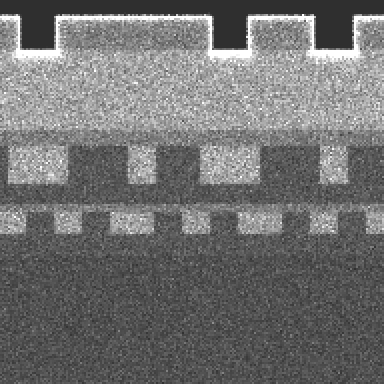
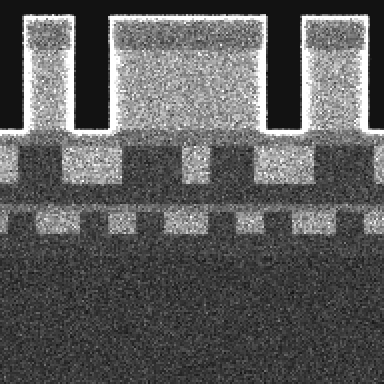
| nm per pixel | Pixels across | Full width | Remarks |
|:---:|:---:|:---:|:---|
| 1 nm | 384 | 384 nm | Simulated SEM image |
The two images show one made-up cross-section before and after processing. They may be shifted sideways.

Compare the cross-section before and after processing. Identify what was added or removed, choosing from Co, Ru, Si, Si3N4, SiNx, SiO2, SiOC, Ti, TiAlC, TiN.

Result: SiO2 removed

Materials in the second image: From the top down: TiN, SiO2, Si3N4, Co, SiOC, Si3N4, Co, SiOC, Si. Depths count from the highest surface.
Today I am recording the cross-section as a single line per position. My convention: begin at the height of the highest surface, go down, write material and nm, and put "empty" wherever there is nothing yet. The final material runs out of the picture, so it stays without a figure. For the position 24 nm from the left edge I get TiN 34, SiO2 80, Si3N4 16, SiOC 58, Si3N4 8, SiOC 44, Si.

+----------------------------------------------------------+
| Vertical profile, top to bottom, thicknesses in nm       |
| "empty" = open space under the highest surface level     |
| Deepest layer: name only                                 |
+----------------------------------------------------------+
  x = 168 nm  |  TiN 34, SiO2 80, Si3N4 16, SiOC 58, Si3N4 8, Co 22, SiOC 22, Si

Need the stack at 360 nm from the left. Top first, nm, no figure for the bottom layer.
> TiN 34, SiO2 80, Si3N4 16, SiOC 58, Si3N4 8, SiOC 44, Si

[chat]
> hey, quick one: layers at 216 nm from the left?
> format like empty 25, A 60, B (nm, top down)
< TiN 34, SiO2 80, Si3N4 16, SiOC 58, Si3N4 8, SiOC 44, Si